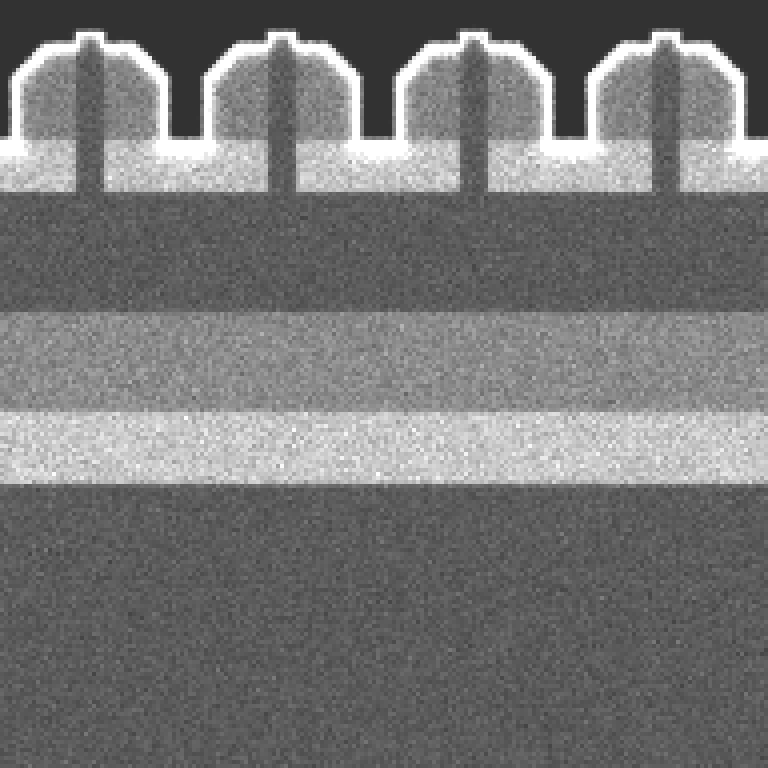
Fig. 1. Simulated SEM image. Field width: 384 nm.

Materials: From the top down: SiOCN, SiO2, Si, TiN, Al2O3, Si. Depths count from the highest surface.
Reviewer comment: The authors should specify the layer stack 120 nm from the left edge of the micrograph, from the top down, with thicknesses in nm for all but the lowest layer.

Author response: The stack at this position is empty 6, SiOCN 48, SiO2 26, Si 60, TiN 50, Al2O3 36, Si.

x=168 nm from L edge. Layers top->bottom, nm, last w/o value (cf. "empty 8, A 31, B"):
empty 12, SiOCN 42, SiO2 26, Si 60, TiN 50, Al2O3 36, Si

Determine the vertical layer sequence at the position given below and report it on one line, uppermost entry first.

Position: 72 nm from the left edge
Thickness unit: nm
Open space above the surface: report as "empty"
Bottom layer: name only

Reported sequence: empty 12, SiOCN 42, SiO2 26, Si 60, TiN 50, Al2O3 36, Si